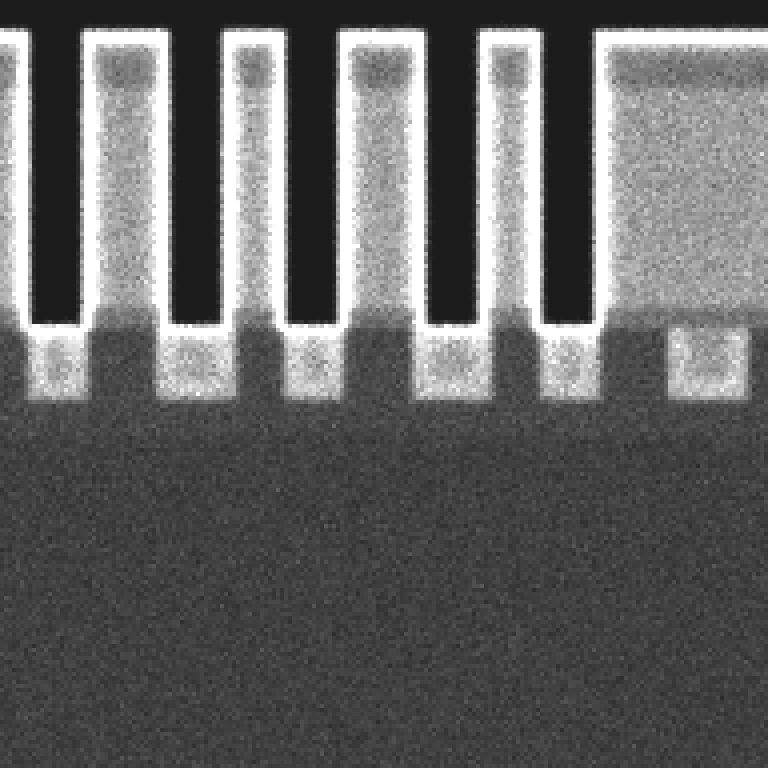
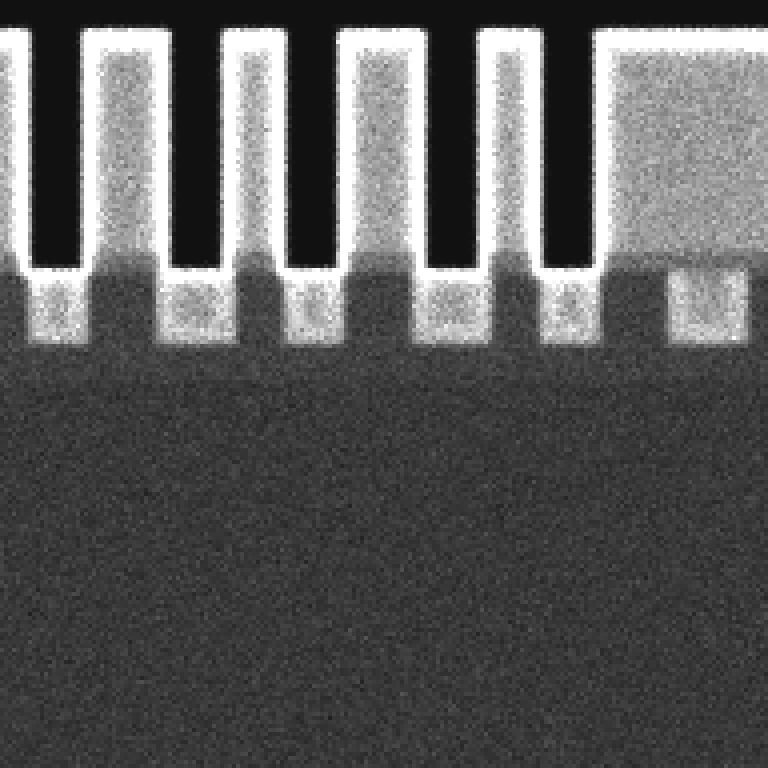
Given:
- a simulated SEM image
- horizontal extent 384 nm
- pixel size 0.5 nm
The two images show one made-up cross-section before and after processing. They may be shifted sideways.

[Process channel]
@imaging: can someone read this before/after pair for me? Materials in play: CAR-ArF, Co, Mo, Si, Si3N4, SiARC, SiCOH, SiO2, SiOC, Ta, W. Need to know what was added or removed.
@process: SiARC removed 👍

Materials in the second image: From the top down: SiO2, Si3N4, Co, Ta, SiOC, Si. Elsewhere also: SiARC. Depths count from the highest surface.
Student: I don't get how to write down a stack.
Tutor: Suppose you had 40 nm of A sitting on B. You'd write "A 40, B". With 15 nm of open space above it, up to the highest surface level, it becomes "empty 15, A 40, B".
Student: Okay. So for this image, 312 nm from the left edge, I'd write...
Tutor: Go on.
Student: SiO2 110, Si3N4 10, SiOC 54, Si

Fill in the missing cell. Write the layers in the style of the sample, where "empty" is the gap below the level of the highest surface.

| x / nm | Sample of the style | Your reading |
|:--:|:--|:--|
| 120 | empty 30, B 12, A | SiO2 110, Si3N4 10, SiOC 54, Si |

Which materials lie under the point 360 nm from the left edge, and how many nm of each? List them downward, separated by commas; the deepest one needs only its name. SiO2 110, Si3N4 10, Co 26, Ta 10, SiOC 18, Si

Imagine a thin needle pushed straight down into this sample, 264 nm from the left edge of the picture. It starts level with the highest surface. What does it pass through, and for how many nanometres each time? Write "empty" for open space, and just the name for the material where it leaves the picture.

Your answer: SiO2 110, Si3N4 10, SiOC 54, Si